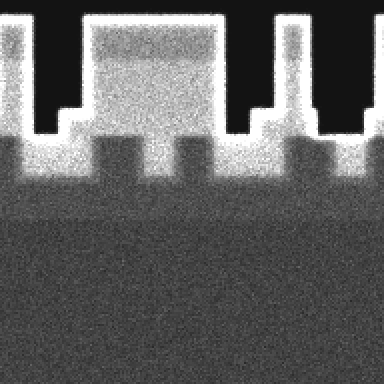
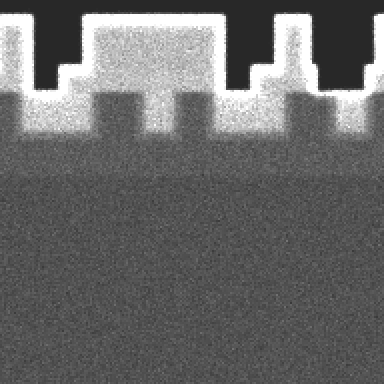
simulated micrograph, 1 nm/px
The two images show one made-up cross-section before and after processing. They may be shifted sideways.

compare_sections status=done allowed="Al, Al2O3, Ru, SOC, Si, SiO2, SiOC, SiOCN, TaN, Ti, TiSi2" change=removed material="SOC"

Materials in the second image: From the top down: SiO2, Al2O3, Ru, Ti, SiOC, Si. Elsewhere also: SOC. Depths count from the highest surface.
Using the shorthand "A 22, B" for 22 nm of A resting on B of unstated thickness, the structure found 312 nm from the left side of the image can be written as empty 50, SiO2 6, Al2O3 20, SiOC 84, Si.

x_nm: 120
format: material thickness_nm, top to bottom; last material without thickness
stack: SiO2 56, Al2O3 20, SiOC 84, Si